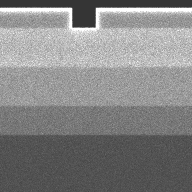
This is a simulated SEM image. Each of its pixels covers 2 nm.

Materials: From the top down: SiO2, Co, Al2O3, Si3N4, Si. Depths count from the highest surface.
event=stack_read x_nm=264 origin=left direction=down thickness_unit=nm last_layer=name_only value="SiO2 40, Co 78, Al2O3 78, Si3N4 58, Si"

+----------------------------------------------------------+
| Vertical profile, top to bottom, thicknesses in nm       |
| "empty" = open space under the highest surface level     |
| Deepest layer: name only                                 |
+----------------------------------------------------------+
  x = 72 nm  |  SiO2 40, Co 78, Al2O3 78, Si3N4 58, Si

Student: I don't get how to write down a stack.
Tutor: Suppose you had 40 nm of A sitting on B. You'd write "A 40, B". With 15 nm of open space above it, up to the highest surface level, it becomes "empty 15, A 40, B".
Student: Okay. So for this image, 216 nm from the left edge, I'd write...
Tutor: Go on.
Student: SiO2 40, Co 78, Al2O3 78, Si3N4 58, Si